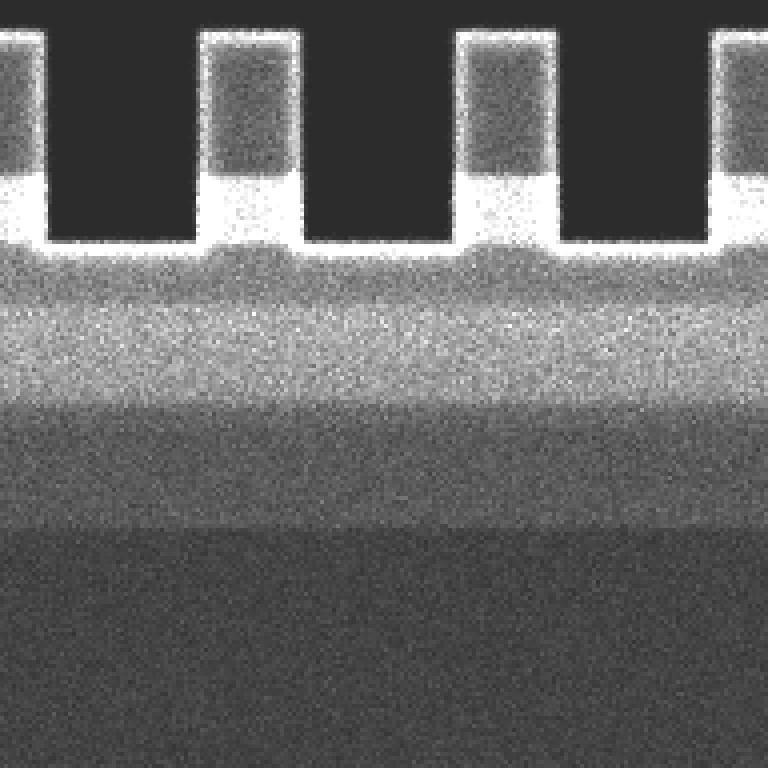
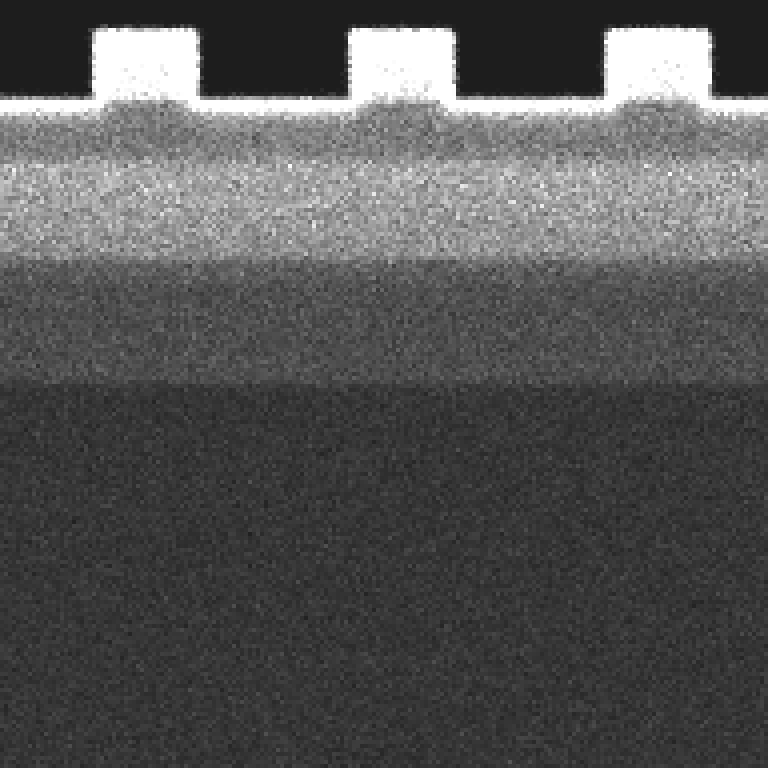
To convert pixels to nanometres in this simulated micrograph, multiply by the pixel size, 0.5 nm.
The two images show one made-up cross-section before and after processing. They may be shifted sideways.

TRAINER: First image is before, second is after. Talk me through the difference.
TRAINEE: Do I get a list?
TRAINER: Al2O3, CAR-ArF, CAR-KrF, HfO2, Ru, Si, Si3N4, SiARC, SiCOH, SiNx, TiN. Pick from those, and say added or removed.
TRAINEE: removed: SiARC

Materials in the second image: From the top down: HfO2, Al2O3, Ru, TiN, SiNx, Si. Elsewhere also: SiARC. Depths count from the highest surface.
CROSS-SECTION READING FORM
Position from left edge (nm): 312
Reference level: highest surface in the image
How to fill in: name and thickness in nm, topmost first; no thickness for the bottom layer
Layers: HfO2 34, Al2O3 30, Ru 50, TiN 12, SiNx 50, Si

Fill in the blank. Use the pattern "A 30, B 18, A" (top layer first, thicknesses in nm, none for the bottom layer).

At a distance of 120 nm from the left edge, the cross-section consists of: empty 34, Al2O3 30, Ru 50, TiN 12, SiNx 50, Si